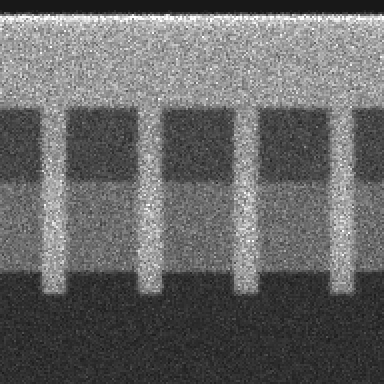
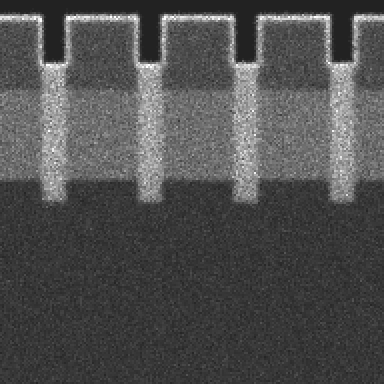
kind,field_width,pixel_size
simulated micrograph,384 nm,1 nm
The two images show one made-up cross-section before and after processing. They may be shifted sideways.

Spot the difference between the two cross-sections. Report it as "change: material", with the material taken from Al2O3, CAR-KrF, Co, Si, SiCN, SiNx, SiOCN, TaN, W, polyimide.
removed: W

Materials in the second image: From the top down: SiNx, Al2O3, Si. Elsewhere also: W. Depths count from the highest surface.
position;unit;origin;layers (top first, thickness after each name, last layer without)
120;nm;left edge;SiNx 74, Al2O3 90, Si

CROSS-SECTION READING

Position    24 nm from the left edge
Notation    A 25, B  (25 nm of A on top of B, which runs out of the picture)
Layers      SiNx 74, Al2O3 90, Si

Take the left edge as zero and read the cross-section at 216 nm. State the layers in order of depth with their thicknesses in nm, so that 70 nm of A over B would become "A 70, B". SiNx 74, Al2O3 90, Si